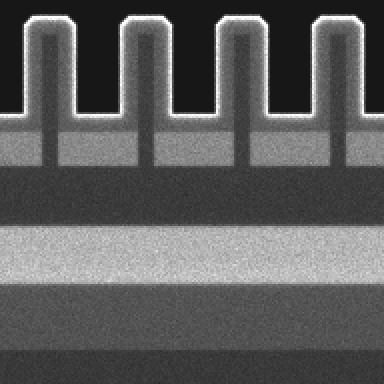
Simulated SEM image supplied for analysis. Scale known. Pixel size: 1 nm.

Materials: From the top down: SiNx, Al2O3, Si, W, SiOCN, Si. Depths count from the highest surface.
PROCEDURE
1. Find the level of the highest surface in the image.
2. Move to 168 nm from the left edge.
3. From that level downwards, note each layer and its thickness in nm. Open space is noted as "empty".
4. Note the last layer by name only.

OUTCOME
empty 6, SiNx 110, Al2O3 34, Si 60, W 58, SiOCN 66, Si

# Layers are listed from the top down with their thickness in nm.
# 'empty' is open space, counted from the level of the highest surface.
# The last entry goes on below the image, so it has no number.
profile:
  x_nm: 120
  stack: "empty 8, SiNx 108, Al2O3 34, Si 60, W 58, SiOCN 66, Si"